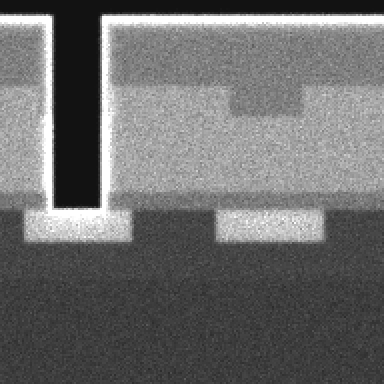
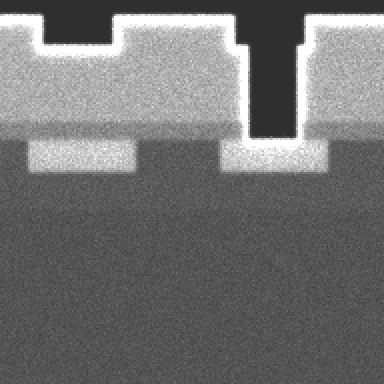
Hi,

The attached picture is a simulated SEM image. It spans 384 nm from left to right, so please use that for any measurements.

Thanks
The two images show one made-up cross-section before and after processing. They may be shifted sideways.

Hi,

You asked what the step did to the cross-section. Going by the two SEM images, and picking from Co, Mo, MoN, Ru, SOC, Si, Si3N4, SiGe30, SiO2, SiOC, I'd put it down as SOC, removed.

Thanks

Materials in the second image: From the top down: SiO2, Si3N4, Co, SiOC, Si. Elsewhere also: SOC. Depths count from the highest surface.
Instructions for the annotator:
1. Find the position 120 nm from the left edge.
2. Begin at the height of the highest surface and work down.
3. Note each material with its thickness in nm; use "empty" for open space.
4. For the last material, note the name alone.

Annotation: SiO2 106, Si3N4 18, Co 32, SiOC 38, Si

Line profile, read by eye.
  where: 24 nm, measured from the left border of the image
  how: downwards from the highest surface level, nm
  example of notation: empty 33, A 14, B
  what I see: SiO2 106, Si3N4 18, SiOC 70, Si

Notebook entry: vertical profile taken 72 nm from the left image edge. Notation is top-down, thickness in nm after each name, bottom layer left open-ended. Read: empty 30, SiO2 76, Si3N4 18, Co 32, SiOC 38, Si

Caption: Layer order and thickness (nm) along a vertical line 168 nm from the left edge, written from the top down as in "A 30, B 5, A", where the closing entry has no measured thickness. SiO2 106, Si3N4 18, SiOC 70, Si